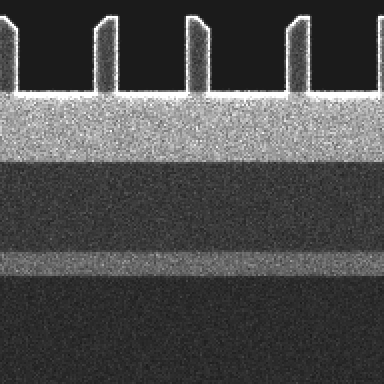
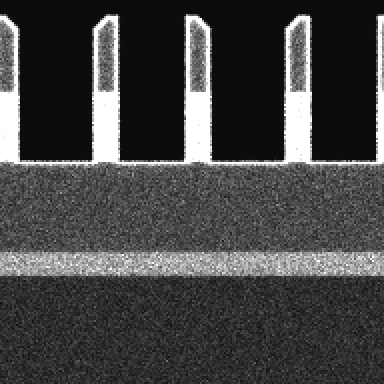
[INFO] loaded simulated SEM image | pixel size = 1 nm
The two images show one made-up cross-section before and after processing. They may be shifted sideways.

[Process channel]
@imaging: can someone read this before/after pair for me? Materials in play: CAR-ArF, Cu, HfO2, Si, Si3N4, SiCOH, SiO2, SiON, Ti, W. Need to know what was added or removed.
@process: HfO2 removed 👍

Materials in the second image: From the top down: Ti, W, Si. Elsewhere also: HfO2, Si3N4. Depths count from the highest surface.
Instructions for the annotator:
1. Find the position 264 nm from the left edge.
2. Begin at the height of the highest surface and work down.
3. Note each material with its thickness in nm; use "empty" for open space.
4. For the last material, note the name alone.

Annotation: empty 146, Ti 90, W 24, Si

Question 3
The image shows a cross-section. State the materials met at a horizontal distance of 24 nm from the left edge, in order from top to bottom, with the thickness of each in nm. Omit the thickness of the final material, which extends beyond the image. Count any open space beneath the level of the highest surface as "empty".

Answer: empty 146, Ti 90, W 24, Si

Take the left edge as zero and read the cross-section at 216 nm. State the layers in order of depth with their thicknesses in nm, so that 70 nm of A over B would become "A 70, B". empty 146, Ti 90, W 24, Si